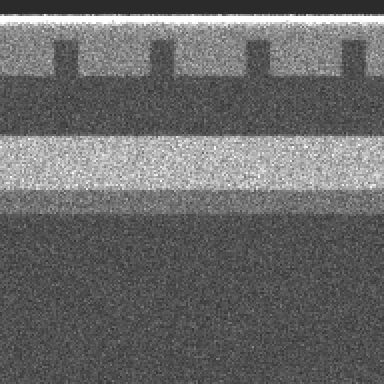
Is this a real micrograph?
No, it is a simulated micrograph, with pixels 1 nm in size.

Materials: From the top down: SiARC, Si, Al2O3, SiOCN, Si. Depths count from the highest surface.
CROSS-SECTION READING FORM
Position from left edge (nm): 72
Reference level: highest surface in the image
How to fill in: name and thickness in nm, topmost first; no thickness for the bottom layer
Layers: SiARC 24, Si 96, Al2O3 54, SiOCN 24, Si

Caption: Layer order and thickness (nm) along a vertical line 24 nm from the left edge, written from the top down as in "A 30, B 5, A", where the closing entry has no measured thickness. SiARC 60, Si 60, Al2O3 54, SiOCN 24, Si